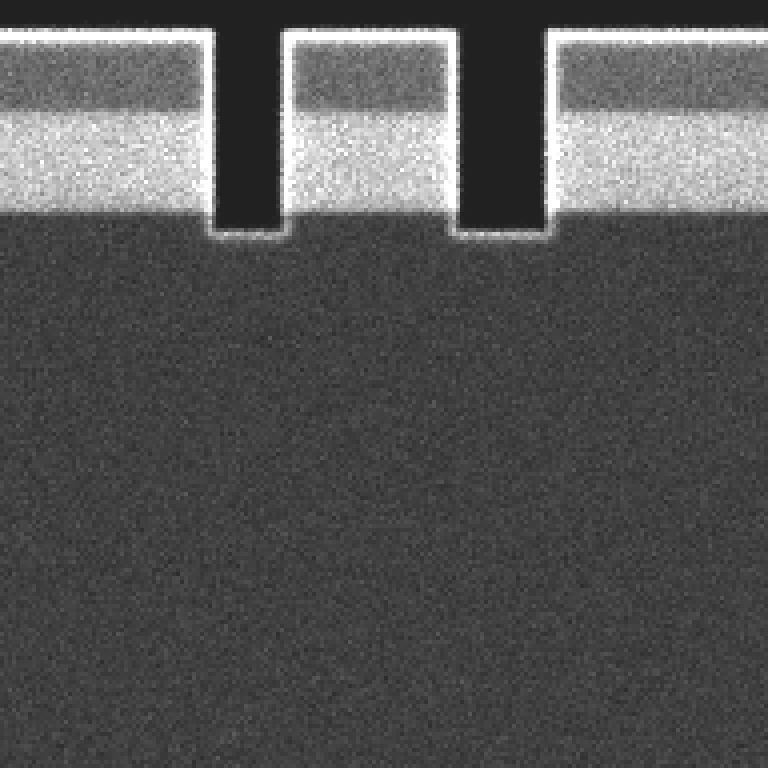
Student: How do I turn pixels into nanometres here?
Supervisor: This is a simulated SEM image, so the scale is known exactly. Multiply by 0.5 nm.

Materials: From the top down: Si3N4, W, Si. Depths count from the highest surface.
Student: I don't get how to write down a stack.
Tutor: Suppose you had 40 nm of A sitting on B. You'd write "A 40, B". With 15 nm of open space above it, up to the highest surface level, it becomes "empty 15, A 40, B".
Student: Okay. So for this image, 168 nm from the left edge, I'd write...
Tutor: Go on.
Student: Si3N4 40, W 50, Si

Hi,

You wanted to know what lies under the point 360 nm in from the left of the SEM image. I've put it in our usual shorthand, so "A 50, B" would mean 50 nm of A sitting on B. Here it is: Si3N4 40, W 50, Si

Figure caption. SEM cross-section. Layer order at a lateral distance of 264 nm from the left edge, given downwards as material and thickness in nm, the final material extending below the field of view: empty 100, Si